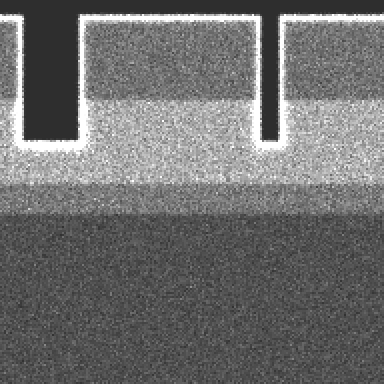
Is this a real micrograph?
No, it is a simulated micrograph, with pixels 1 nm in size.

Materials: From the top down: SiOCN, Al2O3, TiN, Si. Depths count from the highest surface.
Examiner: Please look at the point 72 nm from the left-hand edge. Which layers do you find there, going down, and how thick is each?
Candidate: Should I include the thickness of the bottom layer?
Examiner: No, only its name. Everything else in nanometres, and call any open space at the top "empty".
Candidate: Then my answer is empty 126, Al2O3 42, TiN 30, Si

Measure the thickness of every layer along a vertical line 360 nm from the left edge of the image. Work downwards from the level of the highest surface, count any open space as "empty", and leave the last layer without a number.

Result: SiOCN 84, Al2O3 84, TiN 30, Si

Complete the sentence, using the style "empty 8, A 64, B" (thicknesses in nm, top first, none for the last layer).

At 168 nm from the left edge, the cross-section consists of SiOCN 84, Al2O3 84, TiN 30, Si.